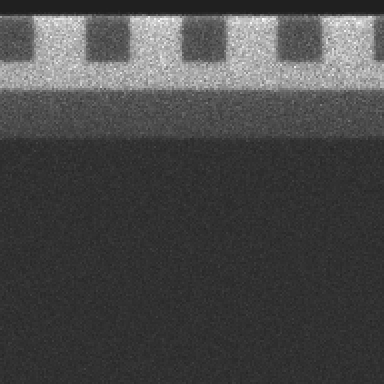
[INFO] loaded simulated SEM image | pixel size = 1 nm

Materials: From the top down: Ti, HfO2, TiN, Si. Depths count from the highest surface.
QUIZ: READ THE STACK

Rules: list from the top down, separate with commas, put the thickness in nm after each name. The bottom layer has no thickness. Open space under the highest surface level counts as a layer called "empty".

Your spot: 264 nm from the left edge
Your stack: HfO2 74, TiN 48, Si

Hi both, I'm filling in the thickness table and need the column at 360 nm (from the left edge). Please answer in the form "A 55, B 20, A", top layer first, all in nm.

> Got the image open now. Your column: HfO2 74, TiN 48, Si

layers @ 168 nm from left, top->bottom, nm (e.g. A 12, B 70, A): HfO2 74, TiN 48, Si